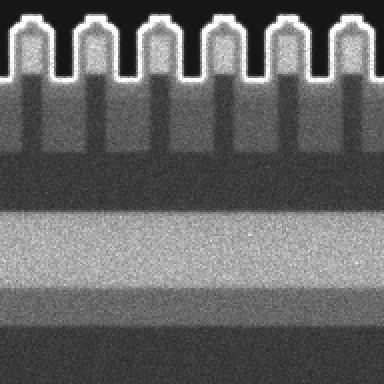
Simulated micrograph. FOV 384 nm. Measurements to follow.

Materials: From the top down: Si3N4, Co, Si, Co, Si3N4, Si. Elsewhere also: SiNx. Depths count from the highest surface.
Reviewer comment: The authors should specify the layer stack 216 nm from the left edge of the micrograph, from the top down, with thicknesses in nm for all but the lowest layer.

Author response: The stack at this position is Si3N4 20, Co 38, Si 138, Co 76, Si3N4 38, Si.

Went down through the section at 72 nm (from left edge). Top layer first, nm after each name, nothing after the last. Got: empty 62, Si3N4 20, SiNx 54, Si 60, Co 76, Si3N4 38, Si